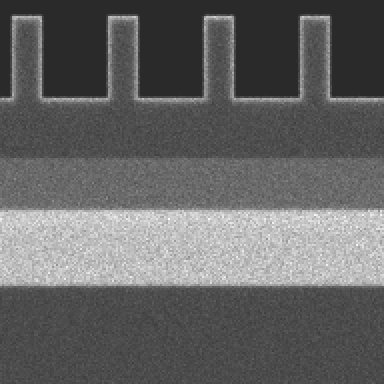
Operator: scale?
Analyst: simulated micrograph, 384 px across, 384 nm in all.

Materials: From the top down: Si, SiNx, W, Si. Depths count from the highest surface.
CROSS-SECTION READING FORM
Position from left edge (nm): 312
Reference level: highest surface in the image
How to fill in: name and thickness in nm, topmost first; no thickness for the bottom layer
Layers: Si 142, SiNx 52, W 76, Si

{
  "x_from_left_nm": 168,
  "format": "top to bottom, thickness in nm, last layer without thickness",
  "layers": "empty 82, Si 60, SiNx 52, W 76, Si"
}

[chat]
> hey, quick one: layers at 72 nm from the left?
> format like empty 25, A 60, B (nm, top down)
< empty 82, Si 60, SiNx 52, W 76, Si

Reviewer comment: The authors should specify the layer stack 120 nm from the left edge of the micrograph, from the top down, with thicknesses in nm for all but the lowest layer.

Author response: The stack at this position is Si 142, SiNx 52, W 76, Si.